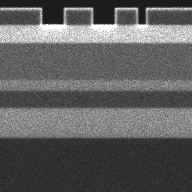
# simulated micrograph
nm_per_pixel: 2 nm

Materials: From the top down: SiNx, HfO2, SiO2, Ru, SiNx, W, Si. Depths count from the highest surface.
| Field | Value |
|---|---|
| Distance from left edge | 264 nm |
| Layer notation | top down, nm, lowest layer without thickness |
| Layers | SiNx 34, HfO2 36, SiO2 74, Ru 22, SiNx 34, W 60, Si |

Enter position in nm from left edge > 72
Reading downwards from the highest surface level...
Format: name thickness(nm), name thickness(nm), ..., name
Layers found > SiNx 34, HfO2 36, SiO2 74, Ru 22, SiNx 34, W 60, Si